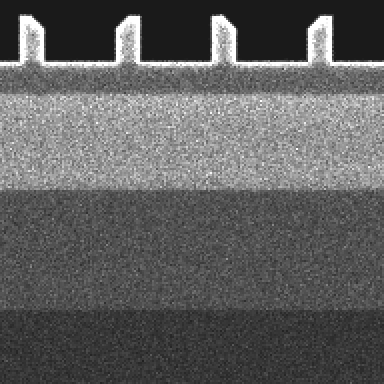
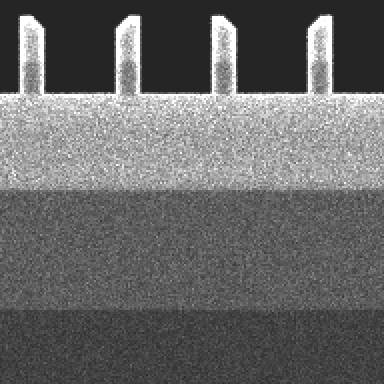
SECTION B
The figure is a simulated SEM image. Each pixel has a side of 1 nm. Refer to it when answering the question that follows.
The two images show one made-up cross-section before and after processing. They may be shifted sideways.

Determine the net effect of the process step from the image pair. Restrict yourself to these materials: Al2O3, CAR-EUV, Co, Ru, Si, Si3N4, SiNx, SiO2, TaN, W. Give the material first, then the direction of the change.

Si3N4: removed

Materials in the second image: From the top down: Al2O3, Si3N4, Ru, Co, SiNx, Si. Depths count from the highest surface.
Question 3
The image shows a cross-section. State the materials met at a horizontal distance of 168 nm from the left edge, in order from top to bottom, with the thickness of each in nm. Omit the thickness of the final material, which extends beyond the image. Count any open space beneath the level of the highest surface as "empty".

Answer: empty 78, Ru 86, Co 10, SiNx 120, Si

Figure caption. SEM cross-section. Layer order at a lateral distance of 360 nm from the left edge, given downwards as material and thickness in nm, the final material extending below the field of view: empty 78, Ru 86, Co 10, SiNx 120, Si